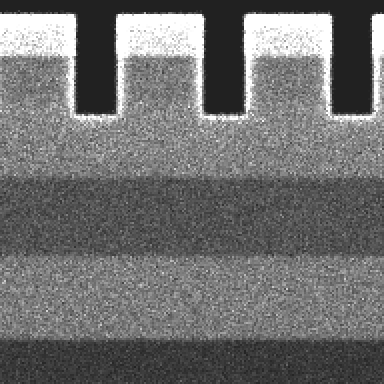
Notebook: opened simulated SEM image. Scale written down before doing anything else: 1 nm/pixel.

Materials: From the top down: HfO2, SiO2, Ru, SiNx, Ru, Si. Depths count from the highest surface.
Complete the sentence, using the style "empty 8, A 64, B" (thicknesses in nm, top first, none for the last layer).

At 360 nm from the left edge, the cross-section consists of empty 100, Ru 62, SiNx 78, Ru 84, Si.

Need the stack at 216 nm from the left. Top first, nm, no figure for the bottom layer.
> empty 100, Ru 62, SiNx 78, Ru 84, Si